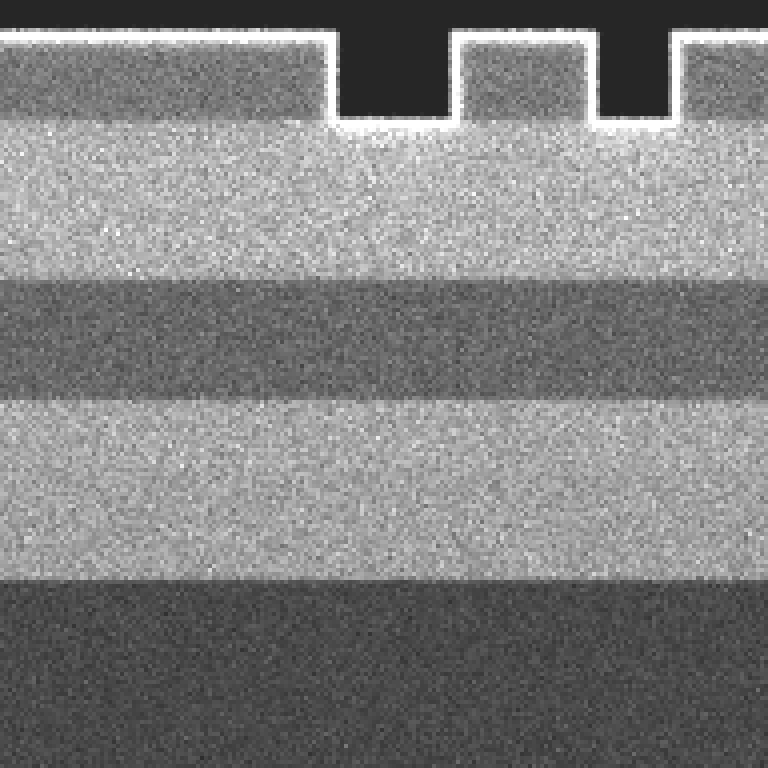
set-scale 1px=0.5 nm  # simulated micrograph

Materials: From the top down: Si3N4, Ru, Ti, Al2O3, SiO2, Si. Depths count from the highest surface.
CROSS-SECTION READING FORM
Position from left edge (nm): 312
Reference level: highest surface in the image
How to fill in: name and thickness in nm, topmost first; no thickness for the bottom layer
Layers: empty 44, Ru 80, Ti 60, Al2O3 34, SiO2 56, Si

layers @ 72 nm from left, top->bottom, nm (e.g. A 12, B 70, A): Si3N4 44, Ru 80, Ti 60, Al2O3 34, SiO2 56, Si